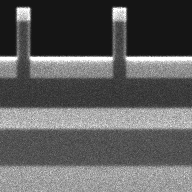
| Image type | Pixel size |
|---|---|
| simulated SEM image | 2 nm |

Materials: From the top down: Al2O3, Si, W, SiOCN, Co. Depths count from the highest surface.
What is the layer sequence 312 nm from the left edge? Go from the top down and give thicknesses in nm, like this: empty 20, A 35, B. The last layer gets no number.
empty 98, Al2O3 42, Si 60, W 42, SiOCN 74, Co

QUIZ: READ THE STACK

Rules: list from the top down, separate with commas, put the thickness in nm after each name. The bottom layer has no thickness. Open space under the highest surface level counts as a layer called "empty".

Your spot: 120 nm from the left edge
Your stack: empty 98, Al2O3 42, Si 60, W 42, SiOCN 74, Co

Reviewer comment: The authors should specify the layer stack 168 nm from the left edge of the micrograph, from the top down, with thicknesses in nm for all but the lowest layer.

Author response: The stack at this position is empty 98, Al2O3 42, Si 60, W 42, SiOCN 74, Co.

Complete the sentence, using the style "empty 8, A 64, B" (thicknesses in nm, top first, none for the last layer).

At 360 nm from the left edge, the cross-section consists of empty 98, Al2O3 42, Si 60, W 42, SiOCN 74, Co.